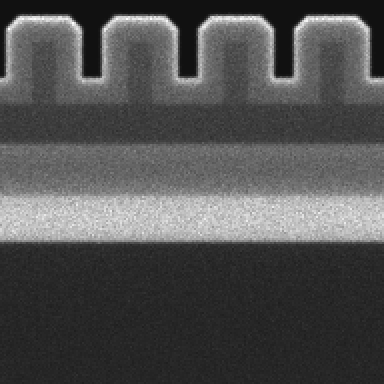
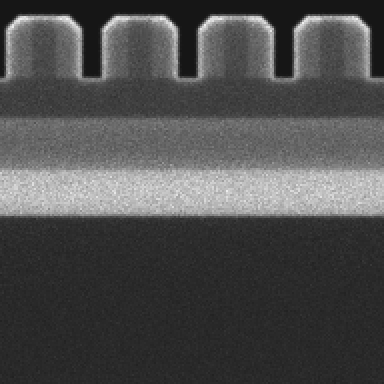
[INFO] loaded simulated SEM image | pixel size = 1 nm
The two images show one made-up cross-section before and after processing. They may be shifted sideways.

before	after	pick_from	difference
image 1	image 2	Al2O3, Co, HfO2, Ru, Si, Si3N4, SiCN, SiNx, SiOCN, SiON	Al2O3 removed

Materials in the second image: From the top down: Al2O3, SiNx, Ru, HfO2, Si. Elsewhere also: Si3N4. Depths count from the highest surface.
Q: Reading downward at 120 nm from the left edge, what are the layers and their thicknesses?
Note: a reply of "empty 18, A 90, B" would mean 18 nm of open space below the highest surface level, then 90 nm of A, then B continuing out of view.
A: Al2O3 62, SiNx 40, Ru 52, HfO2 46, Si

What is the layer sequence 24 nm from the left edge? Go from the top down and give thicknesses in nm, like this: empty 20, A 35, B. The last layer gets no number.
Al2O3 62, SiNx 40, Ru 52, HfO2 46, Si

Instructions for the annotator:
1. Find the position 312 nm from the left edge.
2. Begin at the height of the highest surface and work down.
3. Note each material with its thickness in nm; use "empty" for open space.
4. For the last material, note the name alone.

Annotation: Al2O3 62, SiNx 40, Ru 52, HfO2 46, Si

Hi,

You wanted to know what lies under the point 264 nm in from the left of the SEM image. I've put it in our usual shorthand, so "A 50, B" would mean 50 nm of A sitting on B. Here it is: empty 4, Al2O3 58, SiNx 40, Ru 52, HfO2 46, Si